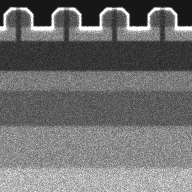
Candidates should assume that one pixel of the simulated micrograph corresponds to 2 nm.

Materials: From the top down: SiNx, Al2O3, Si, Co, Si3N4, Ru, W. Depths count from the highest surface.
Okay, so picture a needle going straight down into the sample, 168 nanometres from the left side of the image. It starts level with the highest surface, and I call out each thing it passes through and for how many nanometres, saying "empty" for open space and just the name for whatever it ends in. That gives empty 38, Al2O3 28, Si 60, Co 40, Si3N4 70, Ru 84, W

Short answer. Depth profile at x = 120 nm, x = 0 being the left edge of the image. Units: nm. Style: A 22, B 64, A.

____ SiNx 38, Al2O3 28, Si 60, Co 40, Si3N4 70, Ru 84, W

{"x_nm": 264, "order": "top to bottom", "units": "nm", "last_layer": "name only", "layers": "empty 38, Al2O3 28, Si 60, Co 40, Si3N4 70, Ru 84, W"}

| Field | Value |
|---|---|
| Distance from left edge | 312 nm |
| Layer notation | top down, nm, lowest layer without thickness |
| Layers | SiNx 38, Al2O3 28, Si 60, Co 40, Si3N4 70, Ru 84, W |